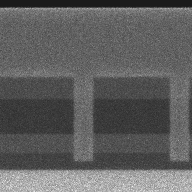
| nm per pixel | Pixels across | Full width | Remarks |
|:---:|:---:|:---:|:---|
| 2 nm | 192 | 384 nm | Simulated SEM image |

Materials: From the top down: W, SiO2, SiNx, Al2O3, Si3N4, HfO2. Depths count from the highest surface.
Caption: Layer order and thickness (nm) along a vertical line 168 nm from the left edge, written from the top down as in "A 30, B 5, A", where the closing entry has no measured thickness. W 306, Si3N4 18, HfO2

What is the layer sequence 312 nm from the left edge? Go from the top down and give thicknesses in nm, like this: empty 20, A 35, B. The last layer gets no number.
W 138, SiO2 44, SiNx 70, Al2O3 38, Si3N4 34, HfO2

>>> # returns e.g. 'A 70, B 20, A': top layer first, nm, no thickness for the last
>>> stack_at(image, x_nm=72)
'W 138, SiO2 44, SiNx 70, Al2O3 38, Si3N4 34, HfO2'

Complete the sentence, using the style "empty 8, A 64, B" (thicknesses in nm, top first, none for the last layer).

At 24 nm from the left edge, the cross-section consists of W 138, SiO2 44, SiNx 70, Al2O3 38, Si3N4 34, HfO2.